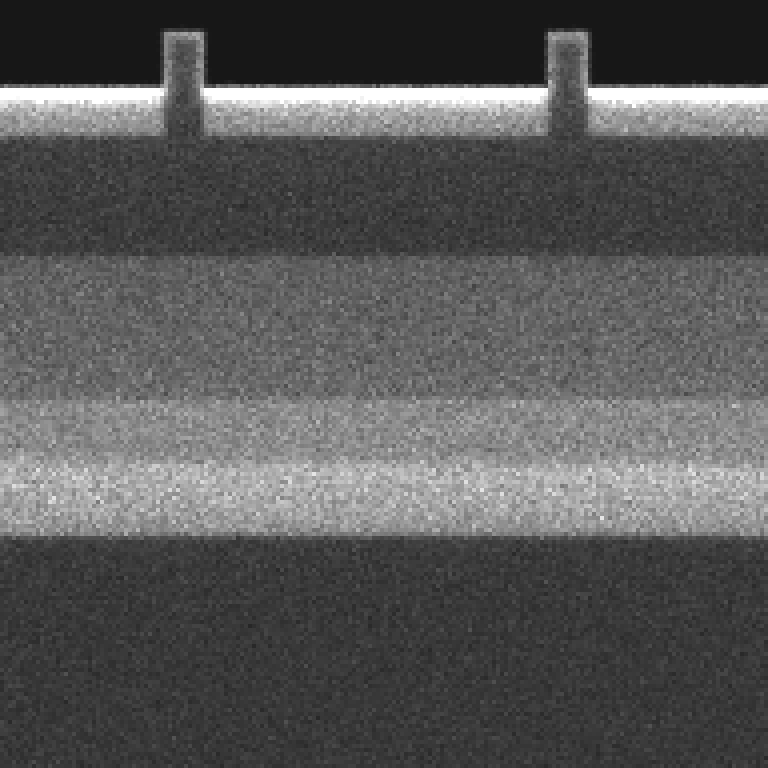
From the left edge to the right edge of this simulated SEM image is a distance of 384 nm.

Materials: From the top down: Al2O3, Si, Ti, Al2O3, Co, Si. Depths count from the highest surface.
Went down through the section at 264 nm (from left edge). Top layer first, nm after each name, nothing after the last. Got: empty 28, Al2O3 24, Si 60, Ti 72, Al2O3 32, Co 36, Si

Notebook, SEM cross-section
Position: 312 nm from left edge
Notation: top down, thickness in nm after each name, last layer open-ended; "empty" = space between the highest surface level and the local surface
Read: empty 28, Al2O3 24, Si 60, Ti 72, Al2O3 32, Co 36, Si